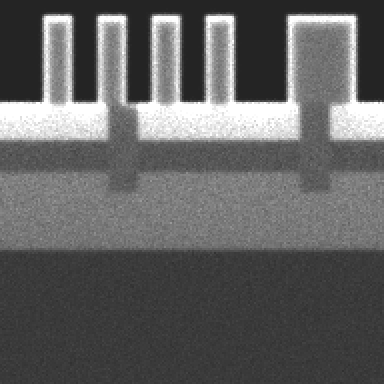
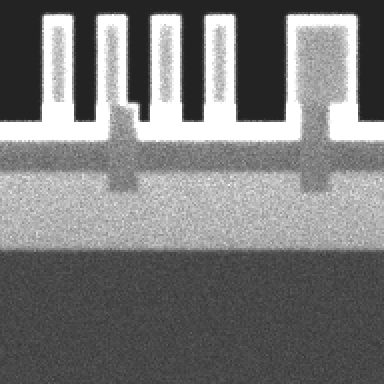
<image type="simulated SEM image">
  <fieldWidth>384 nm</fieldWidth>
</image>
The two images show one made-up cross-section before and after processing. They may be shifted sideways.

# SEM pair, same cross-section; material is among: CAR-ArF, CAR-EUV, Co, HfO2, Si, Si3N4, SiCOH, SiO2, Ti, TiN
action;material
removed;HfO2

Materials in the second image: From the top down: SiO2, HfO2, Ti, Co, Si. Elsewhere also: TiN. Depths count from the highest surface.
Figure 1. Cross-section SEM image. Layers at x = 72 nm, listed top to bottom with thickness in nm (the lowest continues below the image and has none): empty 108, HfO2 16, Ti 32, Co 78, Si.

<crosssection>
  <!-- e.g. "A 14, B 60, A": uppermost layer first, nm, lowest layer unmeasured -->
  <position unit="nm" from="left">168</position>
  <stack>SiO2 88, HfO2 36, Ti 32, Co 78, Si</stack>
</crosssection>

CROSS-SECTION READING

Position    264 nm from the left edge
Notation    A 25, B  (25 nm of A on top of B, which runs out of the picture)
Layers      empty 108, HfO2 16, Ti 32, Co 78, Si